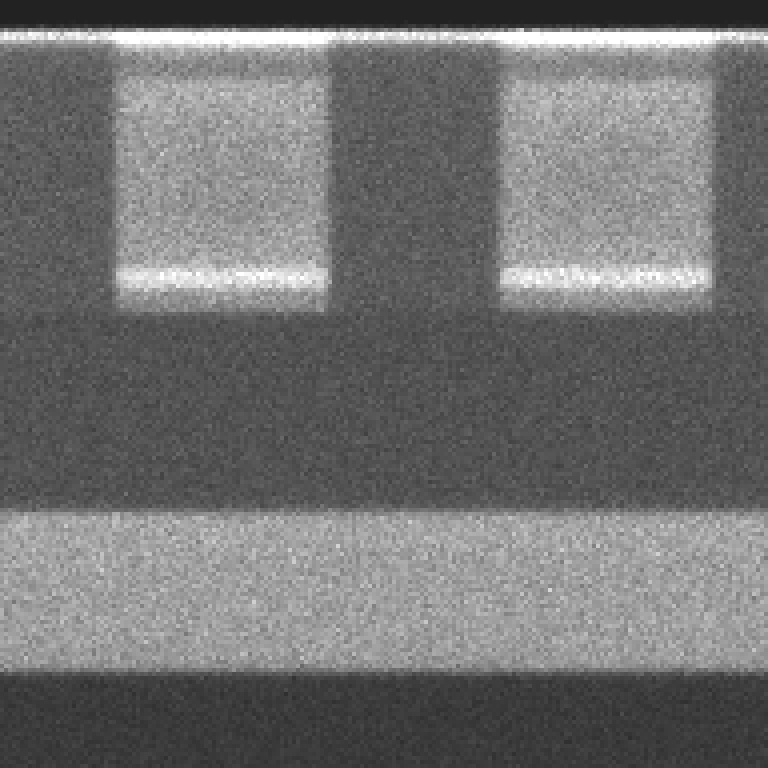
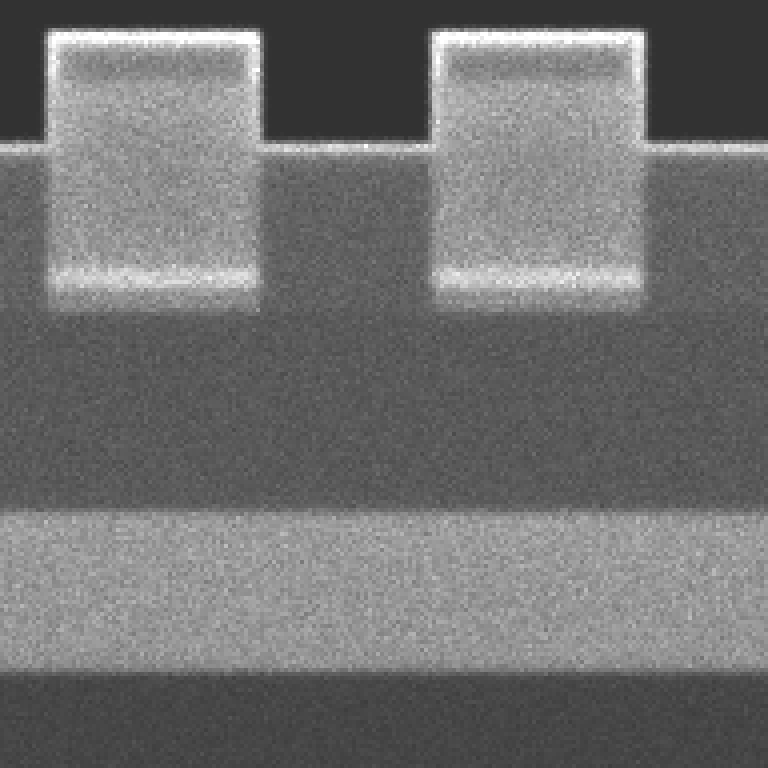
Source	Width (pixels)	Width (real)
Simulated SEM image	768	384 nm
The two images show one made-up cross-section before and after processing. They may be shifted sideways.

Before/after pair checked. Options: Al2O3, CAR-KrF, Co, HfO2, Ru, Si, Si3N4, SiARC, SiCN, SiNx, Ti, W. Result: removed Si3N4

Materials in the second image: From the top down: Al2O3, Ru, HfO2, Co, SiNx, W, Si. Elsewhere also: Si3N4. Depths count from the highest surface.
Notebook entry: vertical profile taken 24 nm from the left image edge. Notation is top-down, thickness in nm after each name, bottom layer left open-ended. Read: Al2O3 24, Ru 94, HfO2 10, Co 12, SiNx 100, W 80, Si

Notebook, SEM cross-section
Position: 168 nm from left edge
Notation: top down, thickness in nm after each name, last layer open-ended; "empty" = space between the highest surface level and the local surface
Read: empty 56, Si3N4 84, SiNx 100, W 80, Si